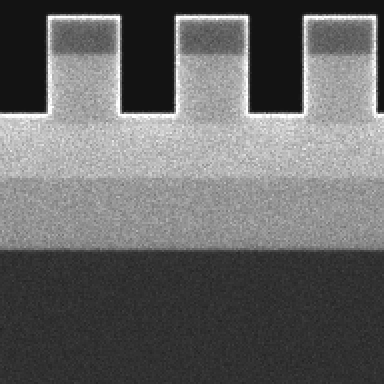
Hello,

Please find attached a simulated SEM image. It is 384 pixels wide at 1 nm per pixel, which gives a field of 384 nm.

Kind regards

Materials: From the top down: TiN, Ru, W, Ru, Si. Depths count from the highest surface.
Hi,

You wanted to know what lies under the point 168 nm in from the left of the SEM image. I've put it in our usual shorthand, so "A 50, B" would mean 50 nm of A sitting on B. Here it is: empty 98, Ru 10, W 54, Ru 72, Si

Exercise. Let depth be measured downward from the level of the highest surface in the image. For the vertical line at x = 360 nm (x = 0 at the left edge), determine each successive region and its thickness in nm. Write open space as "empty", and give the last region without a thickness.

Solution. TiN 38, Ru 70, W 54, Ru 72, Si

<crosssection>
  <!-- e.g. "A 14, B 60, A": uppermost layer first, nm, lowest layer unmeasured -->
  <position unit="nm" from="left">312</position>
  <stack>TiN 38, Ru 70, W 54, Ru 72, Si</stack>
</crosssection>